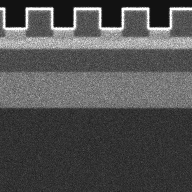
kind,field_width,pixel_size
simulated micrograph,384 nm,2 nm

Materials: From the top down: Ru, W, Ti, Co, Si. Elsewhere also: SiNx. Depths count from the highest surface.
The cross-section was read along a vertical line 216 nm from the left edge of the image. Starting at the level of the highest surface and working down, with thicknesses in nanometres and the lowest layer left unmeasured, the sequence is empty 40, Ru 24, W 18, Ti 46, Co 72, Si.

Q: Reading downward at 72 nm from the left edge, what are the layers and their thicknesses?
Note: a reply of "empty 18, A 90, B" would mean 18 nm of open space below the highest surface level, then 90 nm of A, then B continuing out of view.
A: SiNx 58, W 24, Ti 46, Co 72, Si